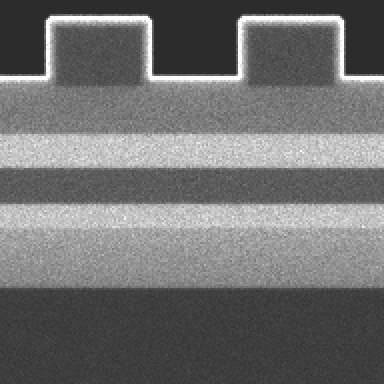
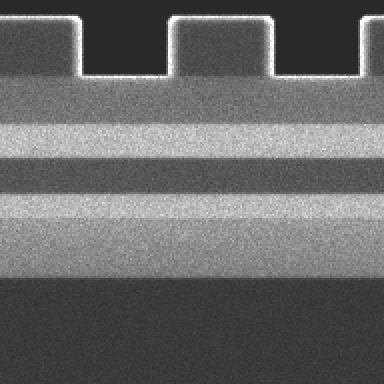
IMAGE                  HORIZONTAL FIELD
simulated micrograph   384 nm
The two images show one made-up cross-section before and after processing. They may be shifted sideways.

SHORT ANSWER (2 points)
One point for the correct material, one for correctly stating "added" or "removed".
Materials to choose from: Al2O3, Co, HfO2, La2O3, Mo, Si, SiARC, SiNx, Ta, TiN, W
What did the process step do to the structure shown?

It removed Al2O3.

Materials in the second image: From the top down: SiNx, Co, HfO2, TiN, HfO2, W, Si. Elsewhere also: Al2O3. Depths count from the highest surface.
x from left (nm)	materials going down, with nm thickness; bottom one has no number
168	empty 4, Al2O3 56, Co 48, HfO2 34, TiN 36, HfO2 24, W 60, Si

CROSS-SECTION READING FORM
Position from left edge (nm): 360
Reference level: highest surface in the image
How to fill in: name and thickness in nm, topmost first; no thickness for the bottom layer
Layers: empty 4, Al2O3 56, Co 48, HfO2 34, TiN 36, HfO2 24, W 60, Si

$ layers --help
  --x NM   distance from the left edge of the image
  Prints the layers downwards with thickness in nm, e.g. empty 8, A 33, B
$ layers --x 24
SiNx 60, Co 48, HfO2 34, TiN 36, HfO2 24, W 60, Si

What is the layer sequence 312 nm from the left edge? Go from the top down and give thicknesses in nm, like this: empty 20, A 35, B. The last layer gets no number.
empty 60, Co 48, HfO2 34, TiN 36, HfO2 24, W 60, Si